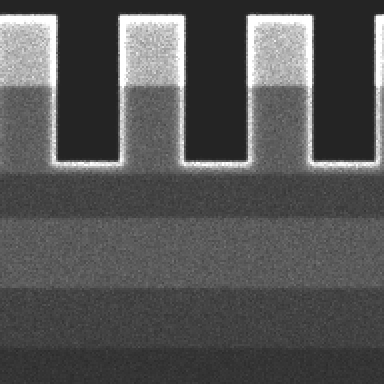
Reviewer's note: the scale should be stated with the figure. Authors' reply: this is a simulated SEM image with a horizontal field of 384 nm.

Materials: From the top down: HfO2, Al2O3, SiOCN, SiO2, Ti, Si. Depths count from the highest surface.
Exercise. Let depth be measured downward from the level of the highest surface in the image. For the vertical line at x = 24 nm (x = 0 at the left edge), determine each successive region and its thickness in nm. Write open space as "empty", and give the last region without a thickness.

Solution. HfO2 70, Al2O3 88, SiOCN 44, SiO2 70, Ti 60, Si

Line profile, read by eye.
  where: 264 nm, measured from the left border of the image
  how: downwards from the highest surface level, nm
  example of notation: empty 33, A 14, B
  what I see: HfO2 70, Al2O3 88, SiOCN 44, SiO2 70, Ti 60, Si